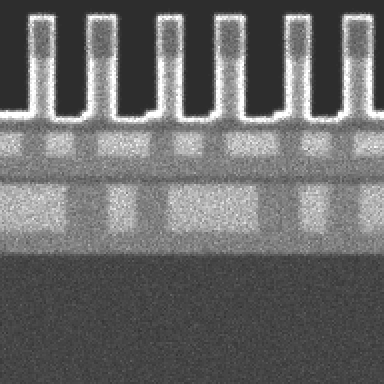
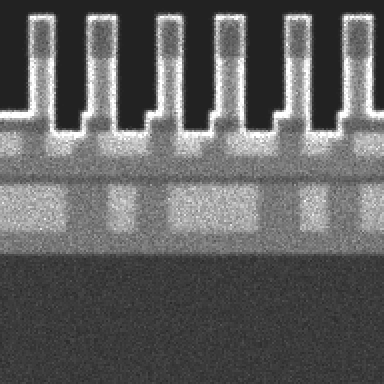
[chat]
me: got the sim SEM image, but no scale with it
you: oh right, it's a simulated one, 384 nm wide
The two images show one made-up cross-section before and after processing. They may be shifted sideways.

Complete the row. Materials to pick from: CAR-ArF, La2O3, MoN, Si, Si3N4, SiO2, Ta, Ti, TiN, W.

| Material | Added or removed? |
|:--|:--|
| Si3N4 | removed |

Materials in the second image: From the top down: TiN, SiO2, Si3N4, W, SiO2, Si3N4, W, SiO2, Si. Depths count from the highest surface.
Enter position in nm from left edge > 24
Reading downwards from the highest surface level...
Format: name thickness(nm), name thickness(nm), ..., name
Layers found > empty 96, SiO2 6, Si3N4 14, SiO2 44, Si3N4 8, W 48, SiO2 22, Si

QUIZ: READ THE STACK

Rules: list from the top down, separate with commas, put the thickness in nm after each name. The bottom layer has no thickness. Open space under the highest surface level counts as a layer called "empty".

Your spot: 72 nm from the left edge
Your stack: empty 116, W 24, SiO2 20, Si3N4 8, SiO2 70, Si